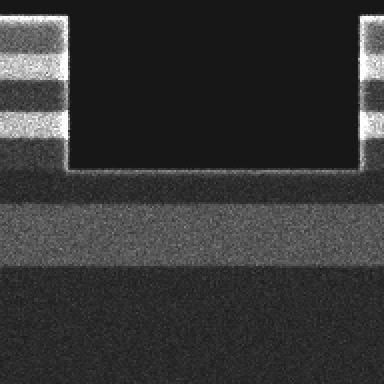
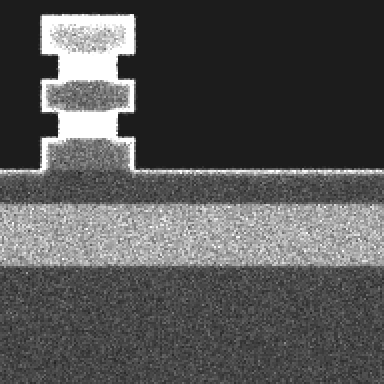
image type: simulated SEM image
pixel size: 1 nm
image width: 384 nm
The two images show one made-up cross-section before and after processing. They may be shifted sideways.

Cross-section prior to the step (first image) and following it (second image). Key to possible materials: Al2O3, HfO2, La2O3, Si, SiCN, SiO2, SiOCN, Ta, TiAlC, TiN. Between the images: HfO2 was removed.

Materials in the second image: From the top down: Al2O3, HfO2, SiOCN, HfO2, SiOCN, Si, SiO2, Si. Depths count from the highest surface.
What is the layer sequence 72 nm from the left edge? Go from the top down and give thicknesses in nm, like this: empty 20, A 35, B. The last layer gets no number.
Al2O3 38, HfO2 26, SiOCN 32, HfO2 26, SiOCN 32, Si 34, SiO2 62, Si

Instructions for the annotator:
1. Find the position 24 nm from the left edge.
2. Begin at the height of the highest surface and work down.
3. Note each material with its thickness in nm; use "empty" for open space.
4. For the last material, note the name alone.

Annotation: empty 154, Si 34, SiO2 62, Si